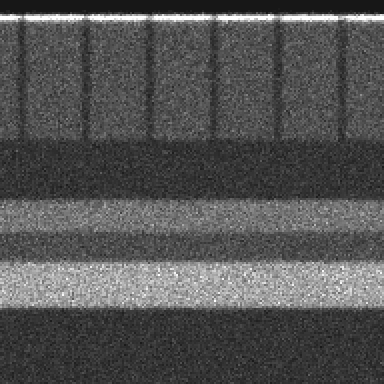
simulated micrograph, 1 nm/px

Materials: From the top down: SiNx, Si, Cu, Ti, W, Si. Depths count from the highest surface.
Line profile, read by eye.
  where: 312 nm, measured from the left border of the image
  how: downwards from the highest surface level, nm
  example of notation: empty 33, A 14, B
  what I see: SiNx 124, Si 60, Cu 32, Ti 30, W 46, Si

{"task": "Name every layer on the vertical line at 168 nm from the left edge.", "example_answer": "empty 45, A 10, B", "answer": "SiNx 124, Si 60, Cu 32, Ti 30, W 46, Si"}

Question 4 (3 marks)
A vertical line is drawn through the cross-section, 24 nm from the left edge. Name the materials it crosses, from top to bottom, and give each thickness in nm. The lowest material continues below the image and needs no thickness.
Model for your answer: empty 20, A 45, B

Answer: Si 184, Cu 32, Ti 30, W 46, Si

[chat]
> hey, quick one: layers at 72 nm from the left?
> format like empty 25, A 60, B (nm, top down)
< SiNx 124, Si 60, Cu 32, Ti 30, W 46, Si